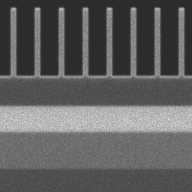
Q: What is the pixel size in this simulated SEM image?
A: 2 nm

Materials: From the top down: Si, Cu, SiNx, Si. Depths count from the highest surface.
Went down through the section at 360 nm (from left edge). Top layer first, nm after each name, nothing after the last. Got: Si 196, Cu 52, SiNx 74, Si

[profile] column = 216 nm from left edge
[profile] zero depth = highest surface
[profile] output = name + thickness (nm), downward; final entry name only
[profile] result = Si 196, Cu 52, SiNx 74, Si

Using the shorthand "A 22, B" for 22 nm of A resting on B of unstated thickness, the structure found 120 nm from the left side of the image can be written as Si 196, Cu 52, SiNx 74, Si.